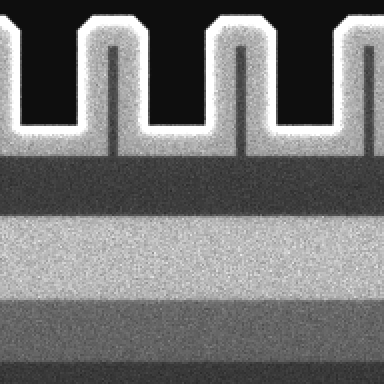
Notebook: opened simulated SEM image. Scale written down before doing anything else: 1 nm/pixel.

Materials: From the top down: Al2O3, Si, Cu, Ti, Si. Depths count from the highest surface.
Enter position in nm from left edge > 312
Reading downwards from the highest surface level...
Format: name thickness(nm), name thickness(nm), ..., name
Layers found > empty 110, Al2O3 30, Si 60, Cu 84, Ti 62, Si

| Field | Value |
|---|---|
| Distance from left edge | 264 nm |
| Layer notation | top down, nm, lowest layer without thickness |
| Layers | empty 4, Al2O3 136, Si 60, Cu 84, Ti 62, Si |